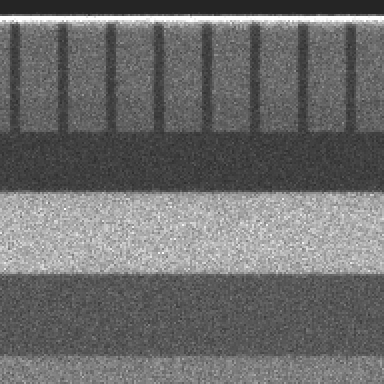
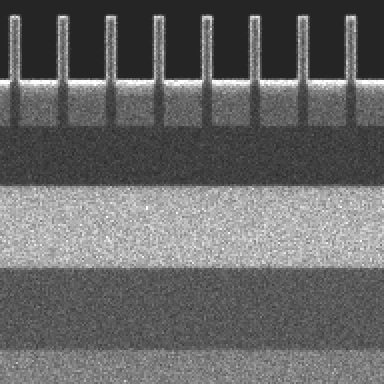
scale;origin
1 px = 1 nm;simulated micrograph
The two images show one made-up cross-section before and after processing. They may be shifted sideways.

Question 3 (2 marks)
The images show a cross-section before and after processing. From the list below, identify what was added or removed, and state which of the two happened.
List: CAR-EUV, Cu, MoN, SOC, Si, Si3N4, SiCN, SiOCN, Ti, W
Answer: SOC was removed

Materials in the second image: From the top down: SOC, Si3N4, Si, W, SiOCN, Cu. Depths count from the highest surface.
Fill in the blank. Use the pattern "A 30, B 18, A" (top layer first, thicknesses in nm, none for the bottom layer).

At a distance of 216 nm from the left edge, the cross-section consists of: empty 64, SOC 12, Si3N4 34, Si 60, W 82, SiOCN 82, Cu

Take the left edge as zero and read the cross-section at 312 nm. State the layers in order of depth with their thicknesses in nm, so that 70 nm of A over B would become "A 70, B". empty 64, SOC 12, Si3N4 34, Si 60, W 82, SiOCN 82, Cu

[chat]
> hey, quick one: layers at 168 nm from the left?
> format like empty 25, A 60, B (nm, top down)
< empty 64, SOC 12, Si3N4 34, Si 60, W 82, SiOCN 82, Cu